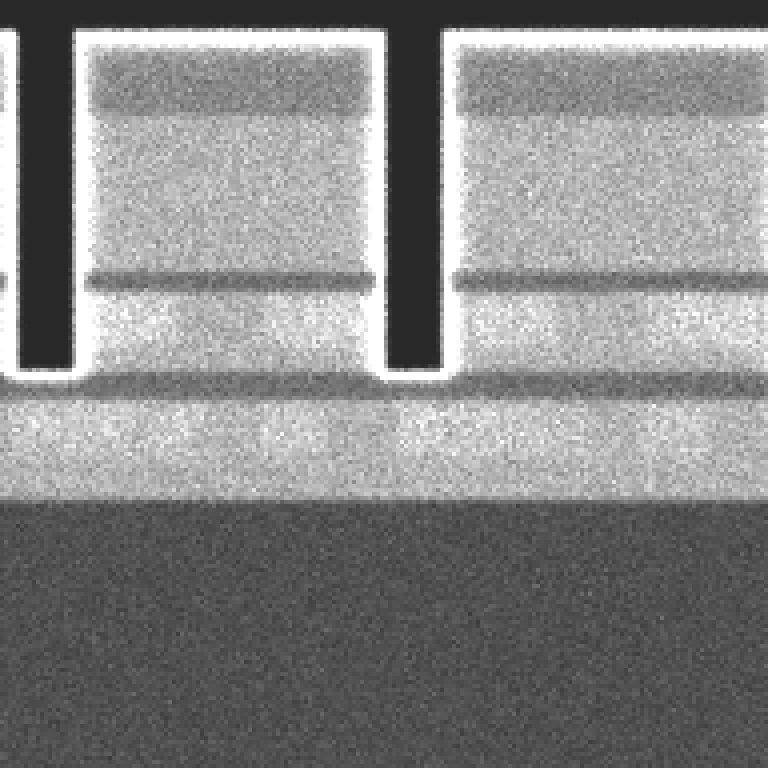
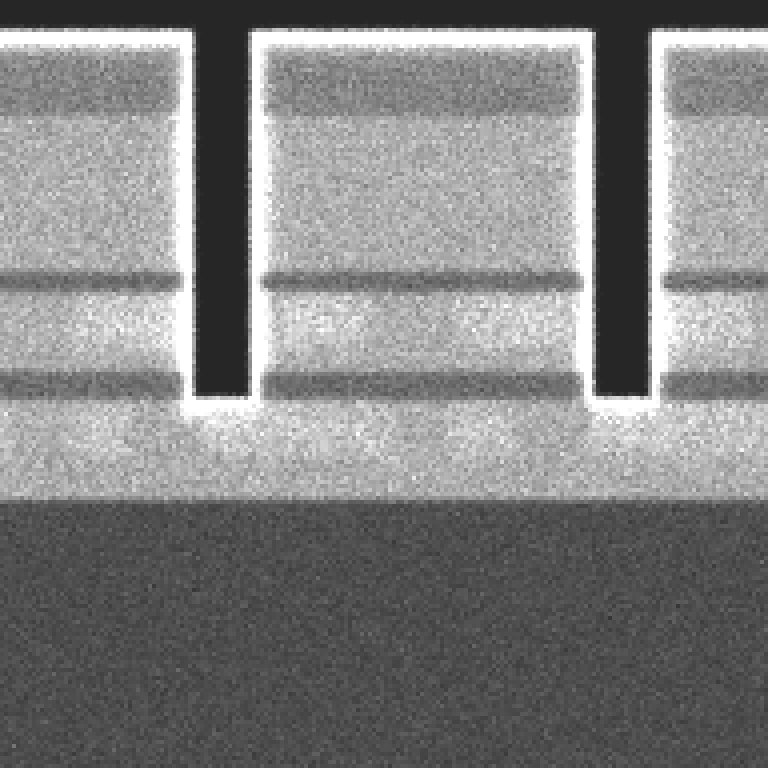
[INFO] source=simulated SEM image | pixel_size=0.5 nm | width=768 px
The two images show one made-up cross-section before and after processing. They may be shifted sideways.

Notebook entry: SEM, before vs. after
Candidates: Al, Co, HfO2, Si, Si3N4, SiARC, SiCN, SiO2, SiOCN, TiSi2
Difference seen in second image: SiCN removed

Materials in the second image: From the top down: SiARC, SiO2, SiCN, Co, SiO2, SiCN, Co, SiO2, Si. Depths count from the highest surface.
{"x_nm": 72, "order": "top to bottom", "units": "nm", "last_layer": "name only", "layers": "SiARC 42, SiO2 78, SiCN 10, Co 28, SiO2 12, SiCN 14, SiO2 50, Si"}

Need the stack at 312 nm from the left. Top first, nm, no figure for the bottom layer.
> empty 184, Co 28, SiO2 22, Si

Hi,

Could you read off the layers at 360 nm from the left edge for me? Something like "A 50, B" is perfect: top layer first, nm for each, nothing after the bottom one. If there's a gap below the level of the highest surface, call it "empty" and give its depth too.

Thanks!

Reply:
SiARC 42, SiO2 78, SiCN 10, Co 28, SiO2 12, SiCN 14, Co 28, SiO2 22, Si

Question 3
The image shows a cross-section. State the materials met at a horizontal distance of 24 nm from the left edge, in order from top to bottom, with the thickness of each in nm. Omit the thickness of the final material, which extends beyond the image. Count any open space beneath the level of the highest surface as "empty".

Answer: SiARC 42, SiO2 78, SiCN 10, SiO2 40, SiCN 14, SiO2 50, Si